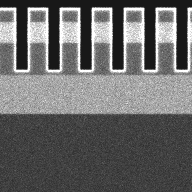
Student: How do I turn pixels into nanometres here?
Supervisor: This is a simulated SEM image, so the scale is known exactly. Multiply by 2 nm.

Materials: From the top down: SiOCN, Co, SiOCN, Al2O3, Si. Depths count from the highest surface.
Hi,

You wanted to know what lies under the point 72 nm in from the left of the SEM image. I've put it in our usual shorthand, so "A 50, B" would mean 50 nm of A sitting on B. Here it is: SiOCN 28, Co 42, SiOCN 64, Al2O3 78, Si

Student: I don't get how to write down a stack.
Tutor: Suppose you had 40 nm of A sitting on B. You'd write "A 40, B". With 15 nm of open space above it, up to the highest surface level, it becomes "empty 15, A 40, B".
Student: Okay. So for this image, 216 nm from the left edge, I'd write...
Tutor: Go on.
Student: SiOCN 28, Co 42, SiOCN 64, Al2O3 78, Si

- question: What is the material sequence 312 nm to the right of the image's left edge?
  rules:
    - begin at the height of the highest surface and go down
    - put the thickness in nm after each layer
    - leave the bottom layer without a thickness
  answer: SiOCN 28, Co 42, SiOCN 64, Al2O3 78, Si